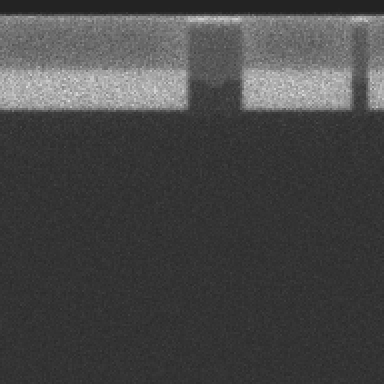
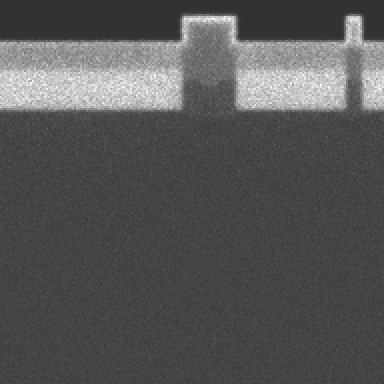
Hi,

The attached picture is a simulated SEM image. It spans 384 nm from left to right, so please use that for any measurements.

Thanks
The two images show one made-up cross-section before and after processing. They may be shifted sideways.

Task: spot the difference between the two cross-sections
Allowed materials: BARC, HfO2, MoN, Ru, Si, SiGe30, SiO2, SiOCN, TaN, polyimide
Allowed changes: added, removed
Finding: removed Ru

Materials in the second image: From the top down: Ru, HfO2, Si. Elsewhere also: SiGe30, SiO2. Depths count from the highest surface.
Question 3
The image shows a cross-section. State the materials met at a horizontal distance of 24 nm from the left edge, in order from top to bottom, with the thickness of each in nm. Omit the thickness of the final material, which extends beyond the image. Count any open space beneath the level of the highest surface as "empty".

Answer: empty 26, Ru 28, HfO2 40, Si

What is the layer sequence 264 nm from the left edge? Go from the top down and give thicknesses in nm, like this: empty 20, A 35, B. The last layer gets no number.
empty 26, Ru 28, HfO2 40, Si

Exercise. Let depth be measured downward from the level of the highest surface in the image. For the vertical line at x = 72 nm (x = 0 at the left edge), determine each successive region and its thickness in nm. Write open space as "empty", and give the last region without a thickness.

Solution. empty 26, Ru 28, HfO2 40, Si